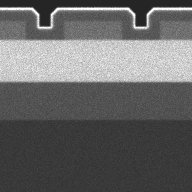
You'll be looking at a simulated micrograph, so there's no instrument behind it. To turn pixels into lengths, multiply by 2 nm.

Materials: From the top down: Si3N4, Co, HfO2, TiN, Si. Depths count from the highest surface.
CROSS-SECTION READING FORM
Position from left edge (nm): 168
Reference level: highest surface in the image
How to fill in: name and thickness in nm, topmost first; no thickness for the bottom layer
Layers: Si3N4 26, Co 38, HfO2 84, TiN 76, Si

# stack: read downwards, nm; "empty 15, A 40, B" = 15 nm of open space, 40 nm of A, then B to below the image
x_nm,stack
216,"Si3N4 26, Co 38, HfO2 84, TiN 76, Si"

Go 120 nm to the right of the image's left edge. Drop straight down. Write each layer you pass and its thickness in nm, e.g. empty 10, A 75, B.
Si3N4 64, HfO2 84, TiN 76, Si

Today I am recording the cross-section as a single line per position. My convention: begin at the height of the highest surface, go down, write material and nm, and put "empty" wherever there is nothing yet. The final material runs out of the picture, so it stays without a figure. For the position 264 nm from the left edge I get empty 8, Si3N4 56, HfO2 84, TiN 76, Si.